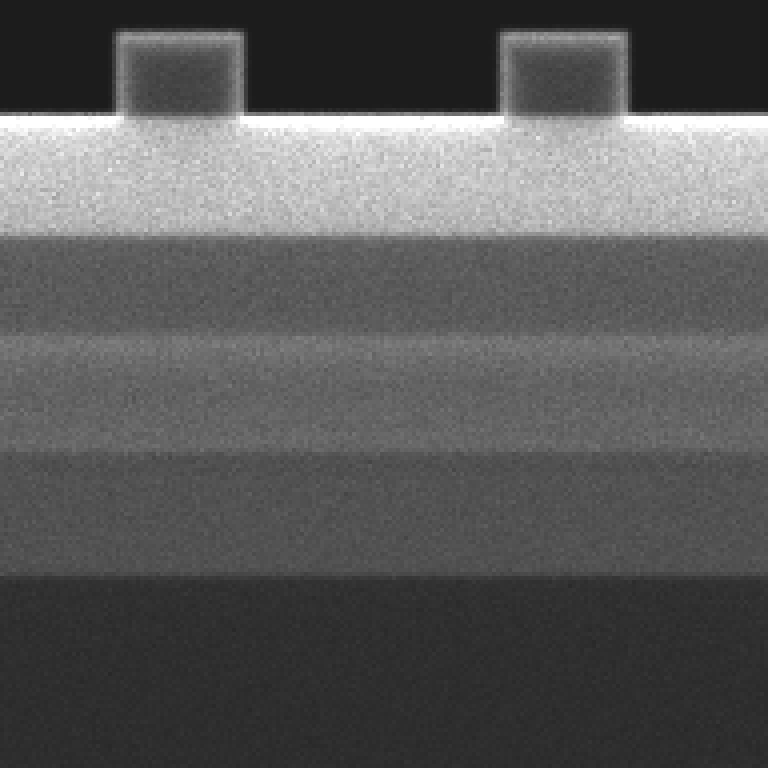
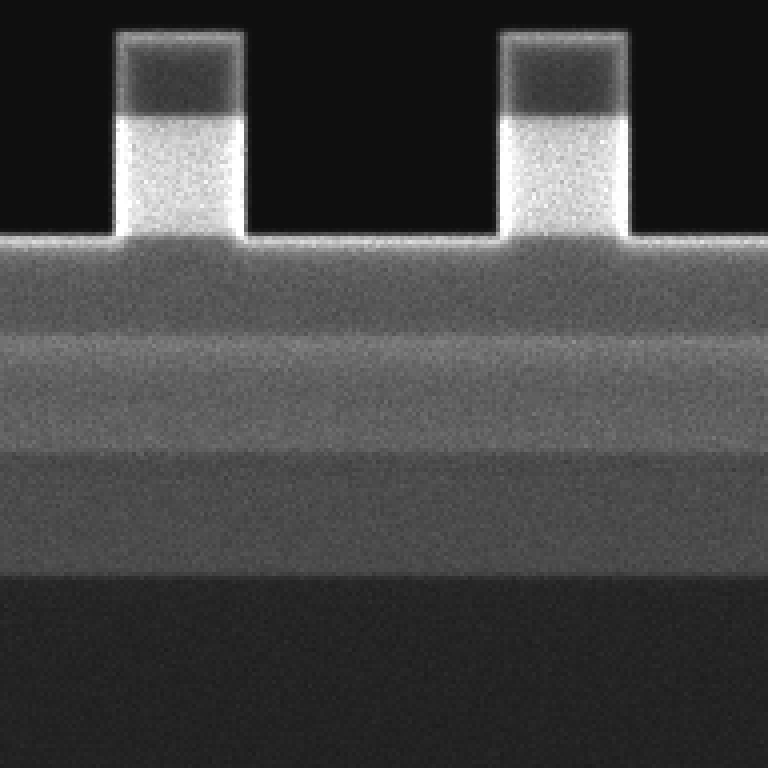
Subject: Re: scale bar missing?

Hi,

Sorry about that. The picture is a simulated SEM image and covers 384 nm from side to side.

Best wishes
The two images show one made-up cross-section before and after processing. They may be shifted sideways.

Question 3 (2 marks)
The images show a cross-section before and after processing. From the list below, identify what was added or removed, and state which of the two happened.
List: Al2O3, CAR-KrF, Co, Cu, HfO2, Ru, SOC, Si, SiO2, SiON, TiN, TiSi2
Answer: HfO2 was removed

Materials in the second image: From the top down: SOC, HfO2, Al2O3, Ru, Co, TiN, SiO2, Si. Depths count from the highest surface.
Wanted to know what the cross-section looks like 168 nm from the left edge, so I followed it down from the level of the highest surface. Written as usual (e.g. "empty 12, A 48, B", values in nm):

empty 102, Al2O3 50, Ru 42, Co 16, TiN 12, SiO2 50, Si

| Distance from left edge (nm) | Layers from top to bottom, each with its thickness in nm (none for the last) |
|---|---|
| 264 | SOC 42, HfO2 60, Al2O3 50, Ru 42, Co 16, TiN 12, SiO2 50, Si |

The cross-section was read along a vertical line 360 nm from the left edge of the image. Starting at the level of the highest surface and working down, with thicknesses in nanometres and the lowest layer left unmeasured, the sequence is empty 102, Al2O3 50, Ru 42, Co 16, TiN 12, SiO2 50, Si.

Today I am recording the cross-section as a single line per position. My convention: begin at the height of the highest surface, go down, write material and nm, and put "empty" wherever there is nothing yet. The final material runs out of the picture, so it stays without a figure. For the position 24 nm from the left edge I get empty 102, Al2O3 50, Ru 42, Co 16, TiN 12, SiO2 50, Si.